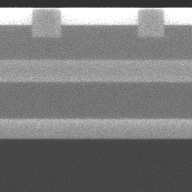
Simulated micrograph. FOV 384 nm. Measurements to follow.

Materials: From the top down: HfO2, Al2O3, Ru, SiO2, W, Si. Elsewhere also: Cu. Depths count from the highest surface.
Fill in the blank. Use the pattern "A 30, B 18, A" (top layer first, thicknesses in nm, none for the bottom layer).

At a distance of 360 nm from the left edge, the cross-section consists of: HfO2 34, Al2O3 70, Ru 44, SiO2 74, W 40, Si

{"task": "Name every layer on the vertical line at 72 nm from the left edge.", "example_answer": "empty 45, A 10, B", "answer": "Cu 58, Al2O3 46, Ru 44, SiO2 74, W 40, Si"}